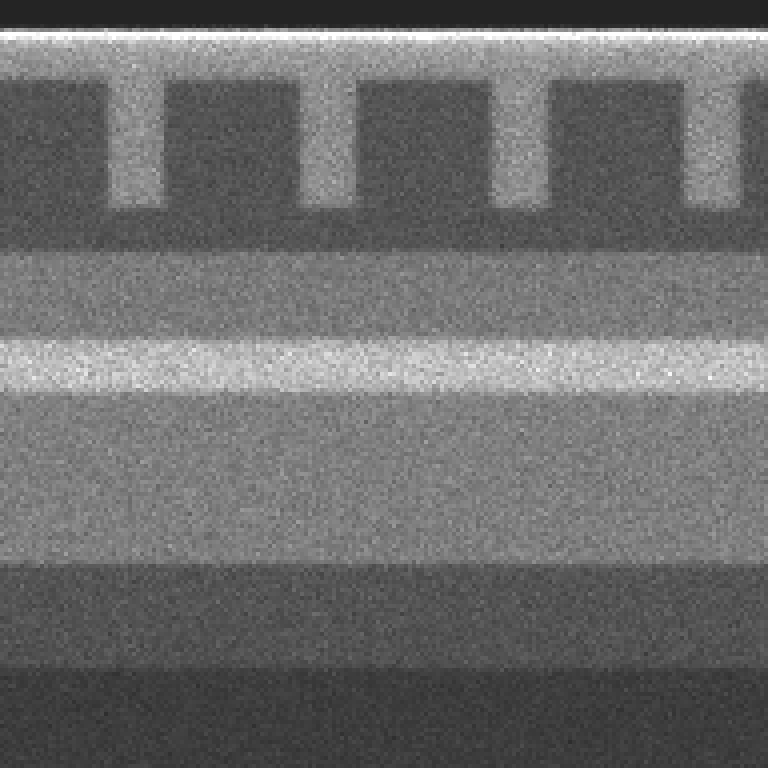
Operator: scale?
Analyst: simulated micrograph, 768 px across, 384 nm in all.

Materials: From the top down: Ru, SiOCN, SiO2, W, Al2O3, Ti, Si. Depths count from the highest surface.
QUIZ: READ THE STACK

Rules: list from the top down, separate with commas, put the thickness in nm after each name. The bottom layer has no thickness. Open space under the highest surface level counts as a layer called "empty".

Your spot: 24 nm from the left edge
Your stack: Ru 24, SiOCN 86, SiO2 44, W 26, Al2O3 86, Ti 52, Si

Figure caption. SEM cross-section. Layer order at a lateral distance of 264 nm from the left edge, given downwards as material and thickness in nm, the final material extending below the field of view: Ru 88, SiOCN 22, SiO2 44, W 26, Al2O3 86, Ti 52, Si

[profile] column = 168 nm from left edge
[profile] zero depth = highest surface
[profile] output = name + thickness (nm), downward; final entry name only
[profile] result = Ru 88, SiOCN 22, SiO2 44, W 26, Al2O3 86, Ti 52, Si